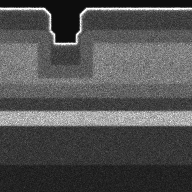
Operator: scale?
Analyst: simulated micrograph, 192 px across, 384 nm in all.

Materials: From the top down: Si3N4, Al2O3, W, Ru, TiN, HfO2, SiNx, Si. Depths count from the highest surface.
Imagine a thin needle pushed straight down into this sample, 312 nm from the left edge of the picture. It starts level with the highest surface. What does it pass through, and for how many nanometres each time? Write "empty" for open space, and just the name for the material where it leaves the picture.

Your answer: Si3N4 44, Al2O3 26, W 82, Ru 28, TiN 26, HfO2 30, SiNx 78, Si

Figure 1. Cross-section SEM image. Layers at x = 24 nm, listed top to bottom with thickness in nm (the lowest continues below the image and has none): Si3N4 44, Al2O3 26, W 82, Ru 28, TiN 26, HfO2 30, SiNx 78, Si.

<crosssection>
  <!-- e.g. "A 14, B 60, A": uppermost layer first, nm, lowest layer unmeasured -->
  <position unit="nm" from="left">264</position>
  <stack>Si3N4 44, Al2O3 26, W 82, Ru 28, TiN 26, HfO2 30, SiNx 78, Si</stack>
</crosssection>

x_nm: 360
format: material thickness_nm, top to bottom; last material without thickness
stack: Si3N4 44, Al2O3 26, W 82, Ru 28, TiN 26, HfO2 30, SiNx 78, Si